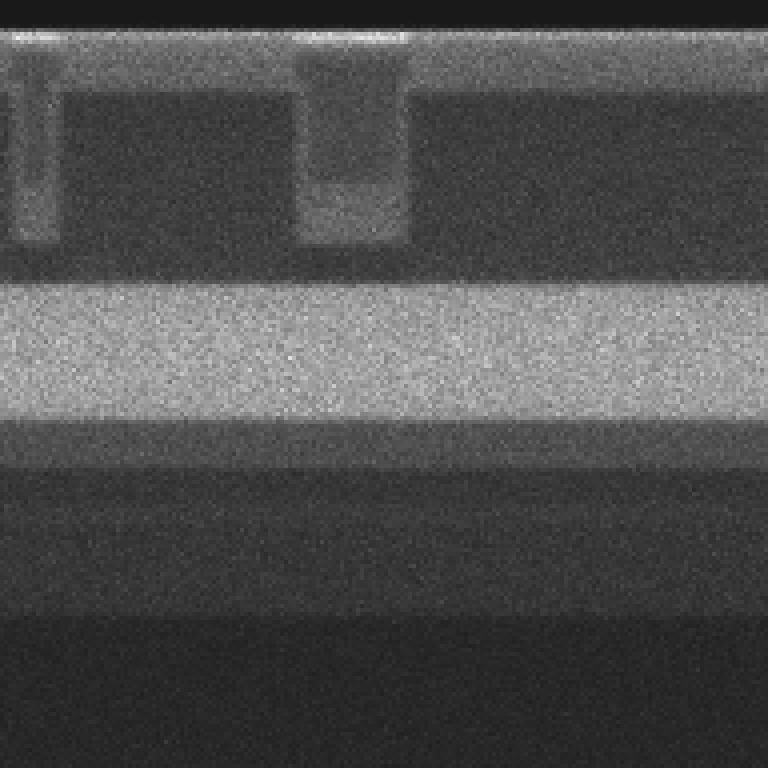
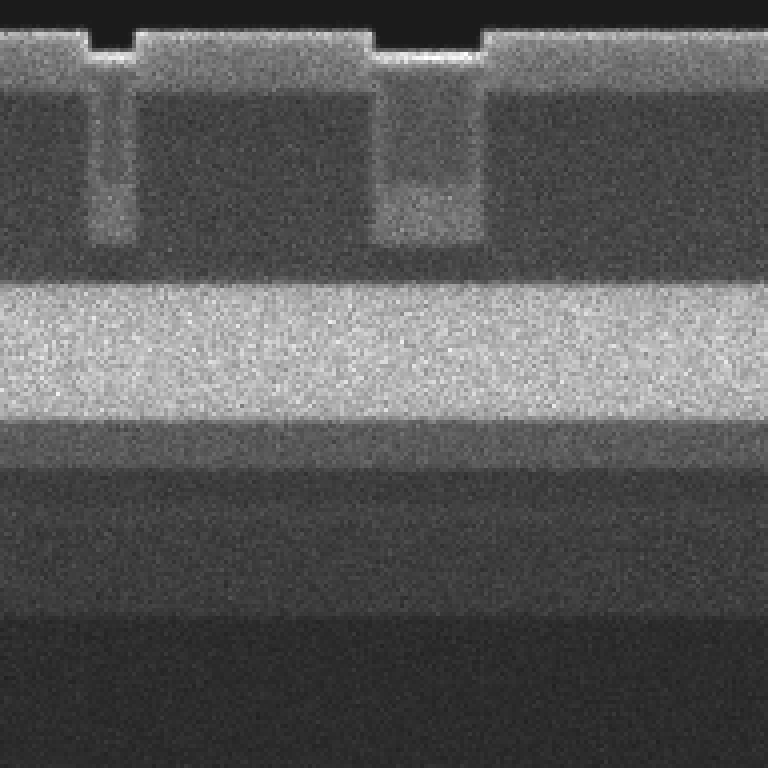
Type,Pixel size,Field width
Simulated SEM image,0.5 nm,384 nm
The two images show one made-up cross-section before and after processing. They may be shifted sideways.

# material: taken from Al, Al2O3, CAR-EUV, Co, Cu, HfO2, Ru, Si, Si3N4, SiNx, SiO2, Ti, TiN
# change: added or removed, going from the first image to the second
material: SiO2
change: removed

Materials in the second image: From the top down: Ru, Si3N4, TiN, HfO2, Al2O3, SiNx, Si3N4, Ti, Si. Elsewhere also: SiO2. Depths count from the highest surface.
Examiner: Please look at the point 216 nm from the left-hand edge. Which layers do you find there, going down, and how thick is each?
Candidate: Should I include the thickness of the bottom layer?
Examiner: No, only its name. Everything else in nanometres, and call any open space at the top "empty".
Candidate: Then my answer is empty 10, SiO2 66, Ru 30, Si3N4 20, HfO2 68, Al2O3 24, SiNx 18, Si3N4 10, Ti 46, Si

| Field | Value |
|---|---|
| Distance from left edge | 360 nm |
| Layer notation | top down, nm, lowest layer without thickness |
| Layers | Ru 30, Si3N4 20, TiN 76, HfO2 68, Al2O3 24, SiNx 18, Si3N4 10, Ti 46, Si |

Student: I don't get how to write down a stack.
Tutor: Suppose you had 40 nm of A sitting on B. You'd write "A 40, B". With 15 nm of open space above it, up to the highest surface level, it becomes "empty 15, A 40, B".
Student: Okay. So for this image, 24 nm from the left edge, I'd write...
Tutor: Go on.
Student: Ru 30, Si3N4 20, TiN 76, HfO2 68, Al2O3 24, SiNx 18, Si3N4 10, Ti 46, Si